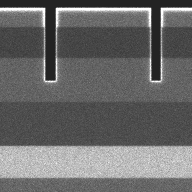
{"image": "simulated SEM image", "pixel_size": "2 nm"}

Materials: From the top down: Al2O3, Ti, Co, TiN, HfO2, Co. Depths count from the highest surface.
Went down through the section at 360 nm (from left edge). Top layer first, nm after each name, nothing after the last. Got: Al2O3 38, Ti 62, Co 88, TiN 88, HfO2 64, Co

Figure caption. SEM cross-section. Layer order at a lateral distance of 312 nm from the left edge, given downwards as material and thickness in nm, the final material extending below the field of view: empty 146, Co 42, TiN 88, HfO2 64, Co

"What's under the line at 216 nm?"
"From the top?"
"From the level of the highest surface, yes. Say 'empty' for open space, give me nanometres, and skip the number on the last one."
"Al2O3 38, Ti 62, Co 88, TiN 88, HfO2 64, Co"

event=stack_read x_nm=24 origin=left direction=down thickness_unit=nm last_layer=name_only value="Al2O3 38, Ti 62, Co 88, TiN 88, HfO2 64, Co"